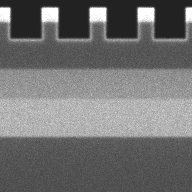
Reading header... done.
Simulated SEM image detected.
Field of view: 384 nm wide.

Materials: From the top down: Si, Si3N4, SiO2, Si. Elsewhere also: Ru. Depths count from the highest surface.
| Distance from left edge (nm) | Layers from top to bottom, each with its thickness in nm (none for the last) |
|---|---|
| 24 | empty 62, Si 60, Si3N4 60, SiO2 76, Si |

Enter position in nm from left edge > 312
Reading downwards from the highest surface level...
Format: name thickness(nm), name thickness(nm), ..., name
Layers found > empty 62, Si 60, Si3N4 60, SiO2 76, Si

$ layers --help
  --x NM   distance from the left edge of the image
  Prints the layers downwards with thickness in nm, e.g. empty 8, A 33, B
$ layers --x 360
empty 62, Si 60, Si3N4 60, SiO2 76, Si